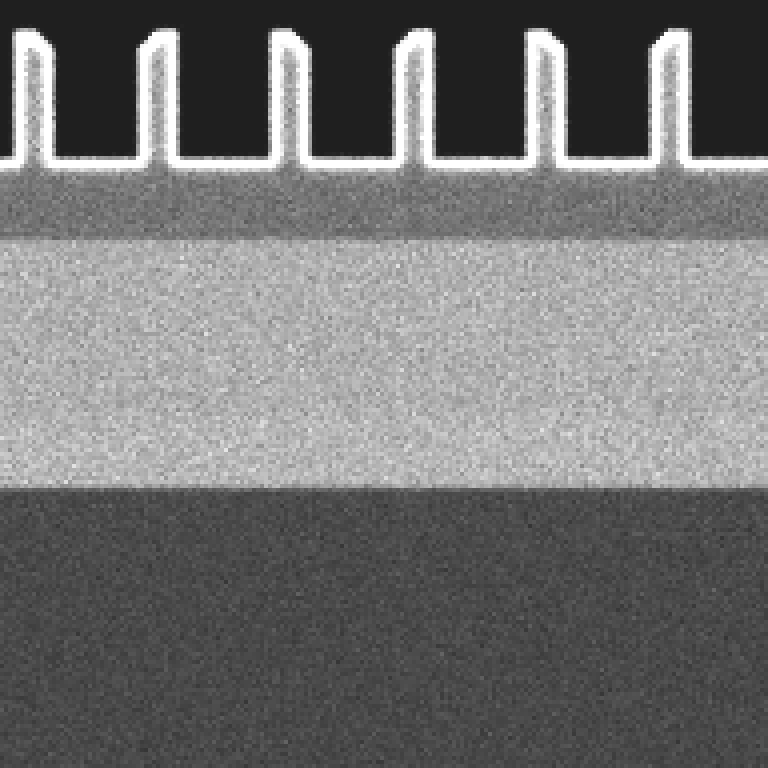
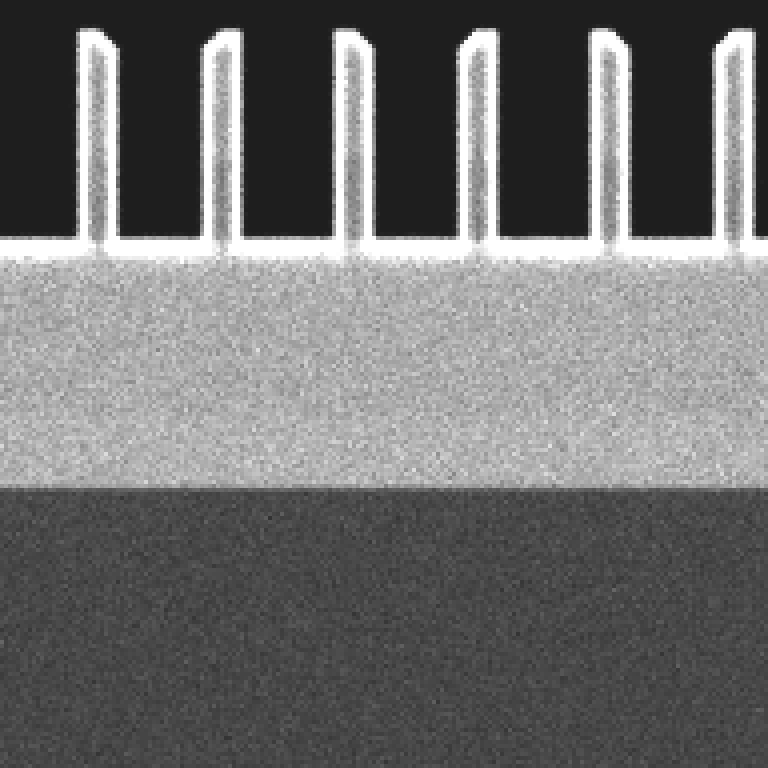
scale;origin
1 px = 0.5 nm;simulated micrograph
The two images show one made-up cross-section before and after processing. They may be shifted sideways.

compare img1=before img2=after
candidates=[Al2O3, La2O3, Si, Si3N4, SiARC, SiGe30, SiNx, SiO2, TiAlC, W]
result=removed:SiNx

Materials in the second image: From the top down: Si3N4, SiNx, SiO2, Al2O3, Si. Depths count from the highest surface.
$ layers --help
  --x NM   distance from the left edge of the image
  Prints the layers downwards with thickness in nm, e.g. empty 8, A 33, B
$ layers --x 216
empty 104, SiO2 88, Al2O3 36, Si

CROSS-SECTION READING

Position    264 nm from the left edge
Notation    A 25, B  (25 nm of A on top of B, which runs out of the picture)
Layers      empty 104, SiO2 88, Al2O3 36, Si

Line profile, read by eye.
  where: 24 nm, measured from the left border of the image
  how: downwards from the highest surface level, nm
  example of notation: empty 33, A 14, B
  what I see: empty 104, SiO2 88, Al2O3 36, Si